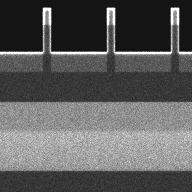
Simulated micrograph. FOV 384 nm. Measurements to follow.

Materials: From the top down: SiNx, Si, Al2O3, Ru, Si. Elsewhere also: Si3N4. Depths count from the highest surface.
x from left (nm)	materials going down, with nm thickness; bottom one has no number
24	empty 88, SiNx 40, Si 60, Al2O3 58, Ru 80, Si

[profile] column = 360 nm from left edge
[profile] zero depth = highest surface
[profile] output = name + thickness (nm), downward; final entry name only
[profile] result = empty 88, SiNx 40, Si 60, Al2O3 58, Ru 80, Si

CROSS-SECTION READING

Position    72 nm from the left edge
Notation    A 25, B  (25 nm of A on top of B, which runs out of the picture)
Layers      empty 88, SiNx 40, Si 60, Al2O3 58, Ru 80, Si